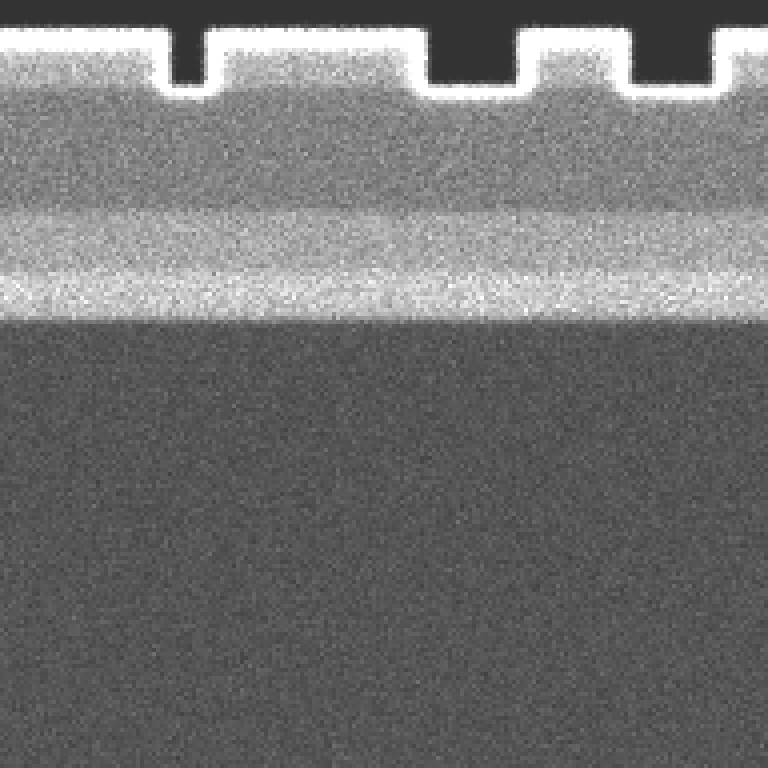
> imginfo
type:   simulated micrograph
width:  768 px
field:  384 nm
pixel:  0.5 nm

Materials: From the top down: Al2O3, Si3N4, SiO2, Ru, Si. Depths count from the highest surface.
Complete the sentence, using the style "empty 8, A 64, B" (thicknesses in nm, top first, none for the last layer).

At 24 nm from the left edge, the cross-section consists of Al2O3 28, Si3N4 62, SiO2 30, Ru 24, Si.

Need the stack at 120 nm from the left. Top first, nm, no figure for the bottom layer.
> Al2O3 28, Si3N4 62, SiO2 30, Ru 24, Si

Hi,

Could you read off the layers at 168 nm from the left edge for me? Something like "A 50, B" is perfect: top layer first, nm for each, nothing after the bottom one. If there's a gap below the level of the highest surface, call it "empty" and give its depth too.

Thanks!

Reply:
Al2O3 28, Si3N4 62, SiO2 30, Ru 24, Si